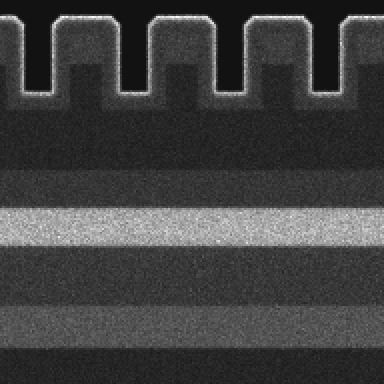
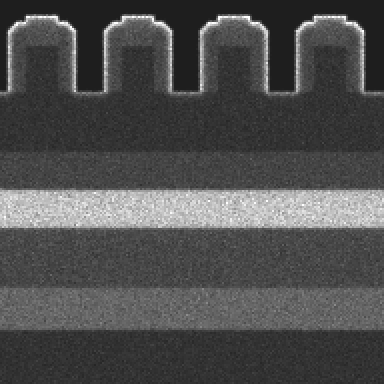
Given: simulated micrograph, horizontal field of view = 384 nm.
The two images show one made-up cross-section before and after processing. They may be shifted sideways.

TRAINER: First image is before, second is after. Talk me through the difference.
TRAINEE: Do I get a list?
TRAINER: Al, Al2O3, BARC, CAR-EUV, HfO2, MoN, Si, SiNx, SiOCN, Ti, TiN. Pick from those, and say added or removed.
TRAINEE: removed: SiNx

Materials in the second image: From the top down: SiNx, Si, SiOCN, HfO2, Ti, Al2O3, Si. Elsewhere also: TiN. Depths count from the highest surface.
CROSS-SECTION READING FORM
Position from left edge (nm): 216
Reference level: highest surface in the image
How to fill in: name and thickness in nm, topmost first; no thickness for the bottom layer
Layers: empty 6, SiNx 70, Si 60, SiOCN 38, HfO2 38, Ti 60, Al2O3 42, Si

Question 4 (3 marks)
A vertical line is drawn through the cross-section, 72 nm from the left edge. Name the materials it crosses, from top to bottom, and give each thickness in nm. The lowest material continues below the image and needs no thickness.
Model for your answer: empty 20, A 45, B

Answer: empty 12, SiNx 64, Si 60, SiOCN 38, HfO2 38, Ti 60, Al2O3 42, Si